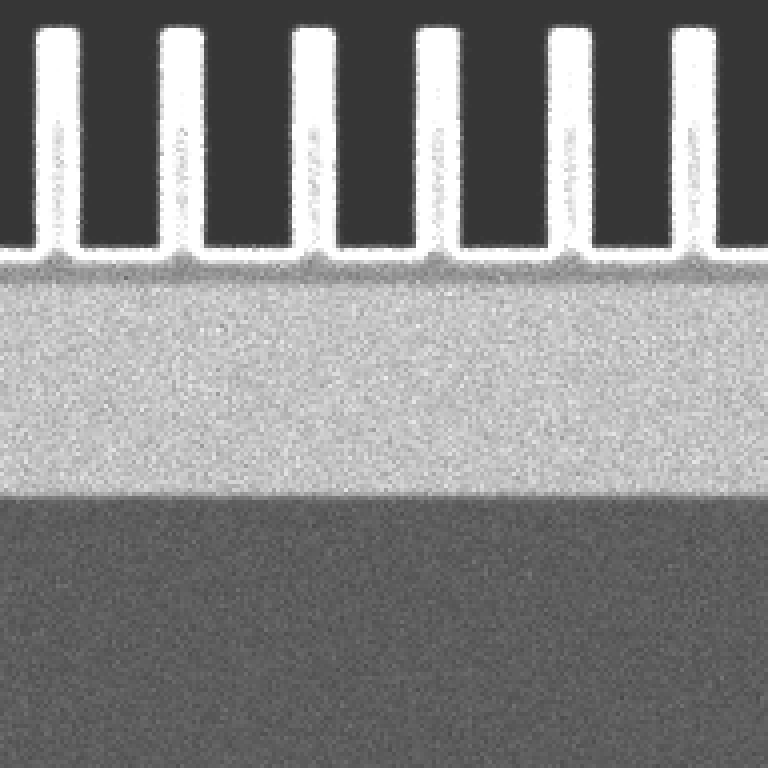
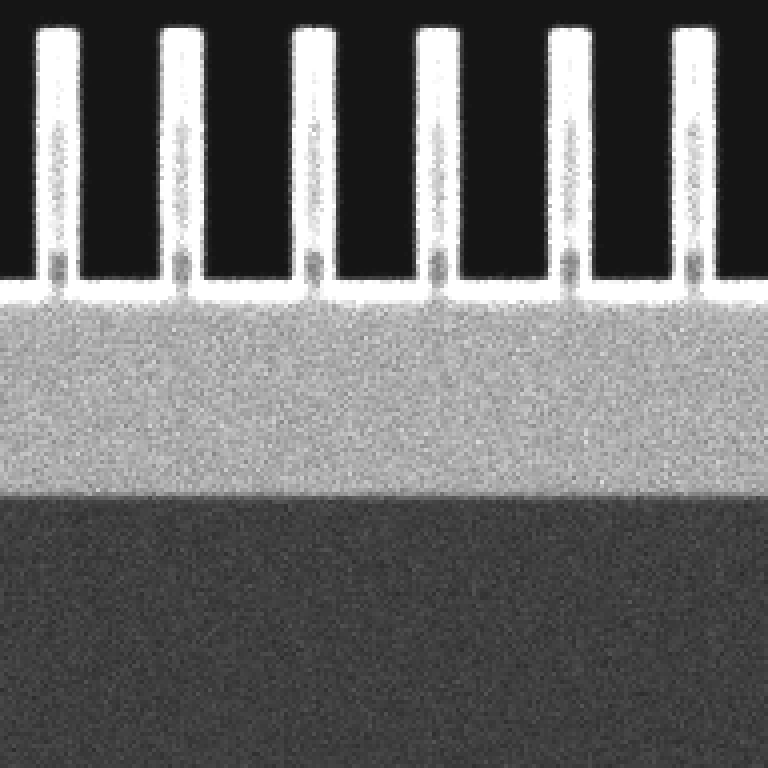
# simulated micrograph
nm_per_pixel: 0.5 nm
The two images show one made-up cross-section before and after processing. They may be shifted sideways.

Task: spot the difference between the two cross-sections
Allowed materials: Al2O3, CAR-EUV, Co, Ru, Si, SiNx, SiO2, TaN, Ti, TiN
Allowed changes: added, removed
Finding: removed TiN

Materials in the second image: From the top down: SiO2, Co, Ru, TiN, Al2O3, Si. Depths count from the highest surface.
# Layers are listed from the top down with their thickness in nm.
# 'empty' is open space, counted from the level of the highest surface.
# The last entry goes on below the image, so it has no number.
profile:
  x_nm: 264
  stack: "empty 126, Al2O3 106, Si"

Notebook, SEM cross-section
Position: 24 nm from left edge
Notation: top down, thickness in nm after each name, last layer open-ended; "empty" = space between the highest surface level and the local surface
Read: SiO2 44, Co 52, Ru 14, TiN 16, Al2O3 106, Si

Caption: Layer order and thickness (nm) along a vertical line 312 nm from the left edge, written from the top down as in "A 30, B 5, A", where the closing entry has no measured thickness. empty 126, Al2O3 106, Si